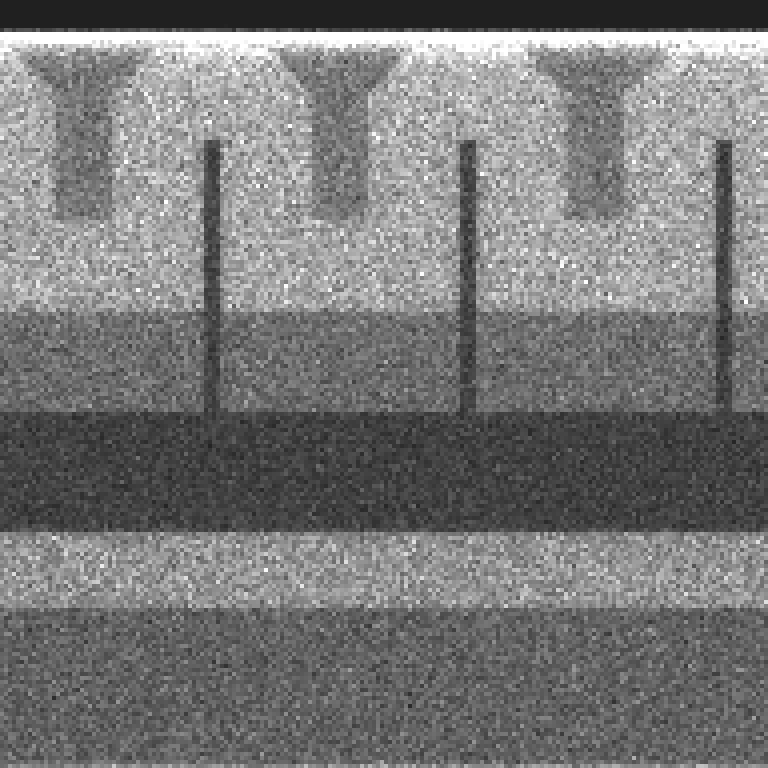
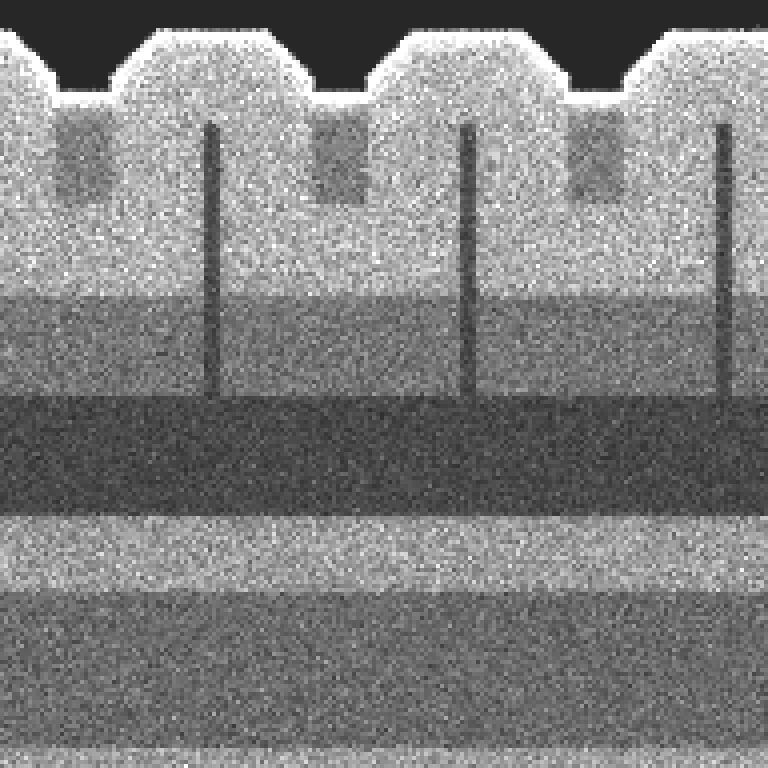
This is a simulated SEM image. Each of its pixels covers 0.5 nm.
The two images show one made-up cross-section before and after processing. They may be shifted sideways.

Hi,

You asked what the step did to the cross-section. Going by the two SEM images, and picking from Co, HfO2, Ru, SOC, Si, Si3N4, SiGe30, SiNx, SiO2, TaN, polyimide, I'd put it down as SOC, removed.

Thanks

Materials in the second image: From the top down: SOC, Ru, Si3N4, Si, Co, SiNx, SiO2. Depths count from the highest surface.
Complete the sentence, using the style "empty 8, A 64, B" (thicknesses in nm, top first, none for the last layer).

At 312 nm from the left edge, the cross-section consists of empty 22, Ru 110, Si3N4 50, Si 60, Co 38, SiNx 78, SiO2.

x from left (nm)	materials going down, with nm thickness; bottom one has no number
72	empty 6, Ru 126, Si3N4 50, Si 60, Co 38, SiNx 78, SiO2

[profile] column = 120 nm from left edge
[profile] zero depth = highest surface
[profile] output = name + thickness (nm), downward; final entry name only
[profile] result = Ru 132, Si3N4 50, Si 60, Co 38, SiNx 78, SiO2